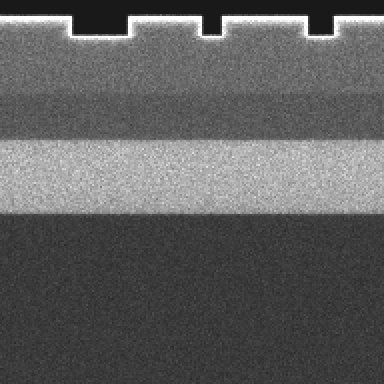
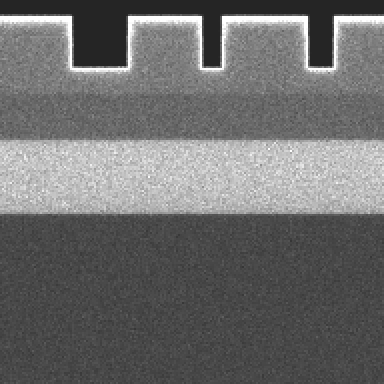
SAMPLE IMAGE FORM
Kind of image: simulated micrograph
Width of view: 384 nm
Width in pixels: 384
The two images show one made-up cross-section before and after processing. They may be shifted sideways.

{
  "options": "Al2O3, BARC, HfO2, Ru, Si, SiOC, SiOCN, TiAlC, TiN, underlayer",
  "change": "removed",
  "material": "TiN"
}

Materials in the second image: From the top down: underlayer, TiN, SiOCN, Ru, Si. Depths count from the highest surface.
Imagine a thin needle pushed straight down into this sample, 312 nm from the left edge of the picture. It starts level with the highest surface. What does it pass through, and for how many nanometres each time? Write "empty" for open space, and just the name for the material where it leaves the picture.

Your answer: empty 52, TiN 26, SiOCN 46, Ru 74, Si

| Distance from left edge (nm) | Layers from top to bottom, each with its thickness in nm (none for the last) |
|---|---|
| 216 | empty 52, TiN 26, SiOCN 46, Ru 74, Si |